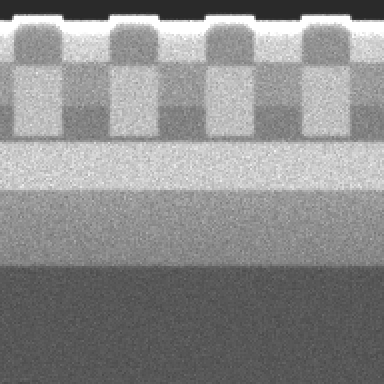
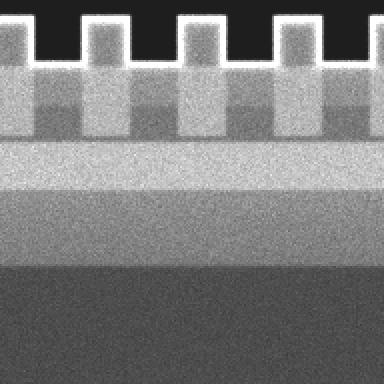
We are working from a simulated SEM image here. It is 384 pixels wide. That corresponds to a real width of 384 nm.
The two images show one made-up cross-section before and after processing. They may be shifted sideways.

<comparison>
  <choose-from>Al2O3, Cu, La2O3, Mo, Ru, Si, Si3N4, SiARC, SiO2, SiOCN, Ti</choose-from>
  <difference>Al2O3 removed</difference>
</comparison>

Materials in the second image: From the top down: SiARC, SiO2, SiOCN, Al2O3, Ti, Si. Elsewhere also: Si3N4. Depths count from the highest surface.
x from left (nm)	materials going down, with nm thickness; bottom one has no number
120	SiARC 50, SiO2 70, SiOCN 6, Al2O3 48, Ti 76, Si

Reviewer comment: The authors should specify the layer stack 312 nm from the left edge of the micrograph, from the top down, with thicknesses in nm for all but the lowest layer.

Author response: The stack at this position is SiARC 50, SiO2 70, SiOCN 6, Al2O3 48, Ti 76, Si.